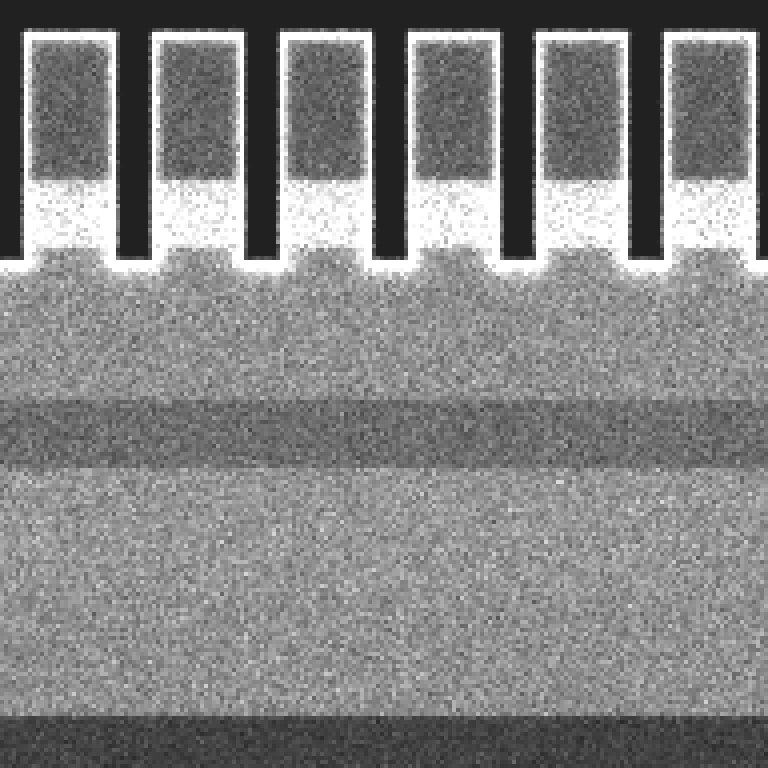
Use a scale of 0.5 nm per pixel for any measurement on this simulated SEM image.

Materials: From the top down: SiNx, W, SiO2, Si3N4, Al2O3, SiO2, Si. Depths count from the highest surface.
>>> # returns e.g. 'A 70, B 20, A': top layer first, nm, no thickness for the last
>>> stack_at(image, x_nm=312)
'SiNx 74, W 34, SiO2 76, Si3N4 34, Al2O3 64, SiO2 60, Si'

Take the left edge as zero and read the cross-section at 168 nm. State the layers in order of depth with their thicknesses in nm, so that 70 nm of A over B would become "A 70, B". SiNx 74, W 34, SiO2 76, Si3N4 34, Al2O3 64, SiO2 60, Si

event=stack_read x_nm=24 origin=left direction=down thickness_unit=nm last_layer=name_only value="SiNx 74, W 34, SiO2 76, Si3N4 34, Al2O3 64, SiO2 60, Si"